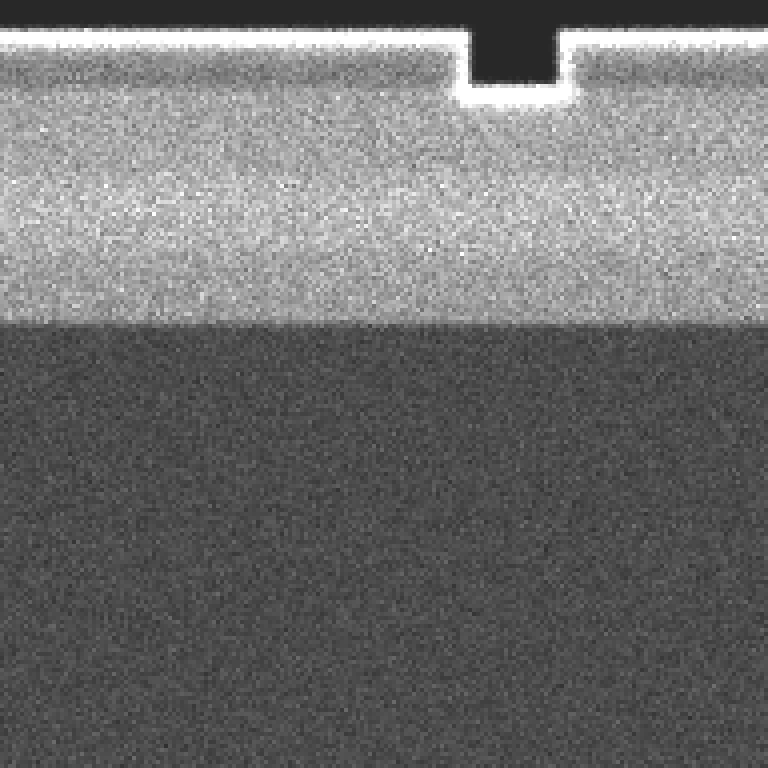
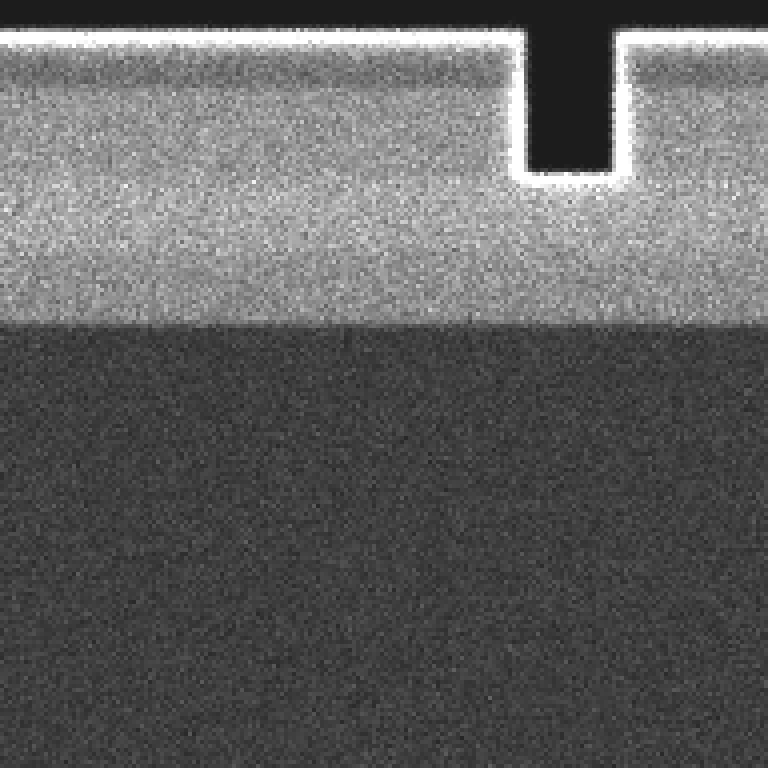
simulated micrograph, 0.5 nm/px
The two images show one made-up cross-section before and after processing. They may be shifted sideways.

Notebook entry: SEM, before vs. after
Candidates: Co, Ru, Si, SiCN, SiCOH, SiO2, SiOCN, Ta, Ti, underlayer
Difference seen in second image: SiO2 removed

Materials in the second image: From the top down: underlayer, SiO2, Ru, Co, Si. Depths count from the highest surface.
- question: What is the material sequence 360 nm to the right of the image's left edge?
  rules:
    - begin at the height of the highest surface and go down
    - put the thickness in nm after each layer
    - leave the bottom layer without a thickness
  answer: underlayer 28, SiO2 44, Ru 38, Co 36, Si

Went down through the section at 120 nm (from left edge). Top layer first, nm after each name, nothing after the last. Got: underlayer 28, SiO2 44, Ru 38, Co 36, Si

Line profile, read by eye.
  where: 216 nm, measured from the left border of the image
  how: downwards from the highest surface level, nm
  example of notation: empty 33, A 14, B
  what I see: underlayer 28, SiO2 44, Ru 38, Co 36, Si